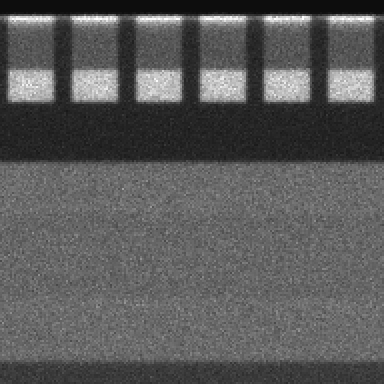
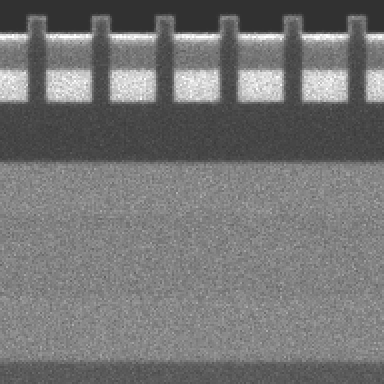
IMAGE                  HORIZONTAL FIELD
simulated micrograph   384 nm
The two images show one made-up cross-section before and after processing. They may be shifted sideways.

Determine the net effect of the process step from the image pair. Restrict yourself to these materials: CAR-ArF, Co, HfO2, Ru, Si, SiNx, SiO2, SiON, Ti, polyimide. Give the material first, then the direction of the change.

SiO2: removed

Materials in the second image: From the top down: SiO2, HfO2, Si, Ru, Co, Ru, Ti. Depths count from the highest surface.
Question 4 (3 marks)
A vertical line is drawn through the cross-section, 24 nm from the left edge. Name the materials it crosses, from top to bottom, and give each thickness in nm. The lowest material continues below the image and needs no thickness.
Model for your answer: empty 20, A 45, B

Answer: empty 18, SiO2 36, HfO2 32, Si 60, Ru 52, Co 84, Ru 64, Ti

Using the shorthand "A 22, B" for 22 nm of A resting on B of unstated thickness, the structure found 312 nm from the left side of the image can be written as empty 18, SiO2 36, HfO2 32, Si 60, Ru 52, Co 84, Ru 64, Ti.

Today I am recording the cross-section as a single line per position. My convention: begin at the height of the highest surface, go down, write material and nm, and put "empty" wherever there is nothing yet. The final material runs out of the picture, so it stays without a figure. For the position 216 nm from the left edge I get empty 18, SiO2 36, HfO2 32, Si 60, Ru 52, Co 84, Ru 64, Ti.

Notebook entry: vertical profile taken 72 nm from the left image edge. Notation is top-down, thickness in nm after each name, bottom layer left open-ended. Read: empty 18, SiO2 36, HfO2 32, Si 60, Ru 52, Co 84, Ru 64, Ti